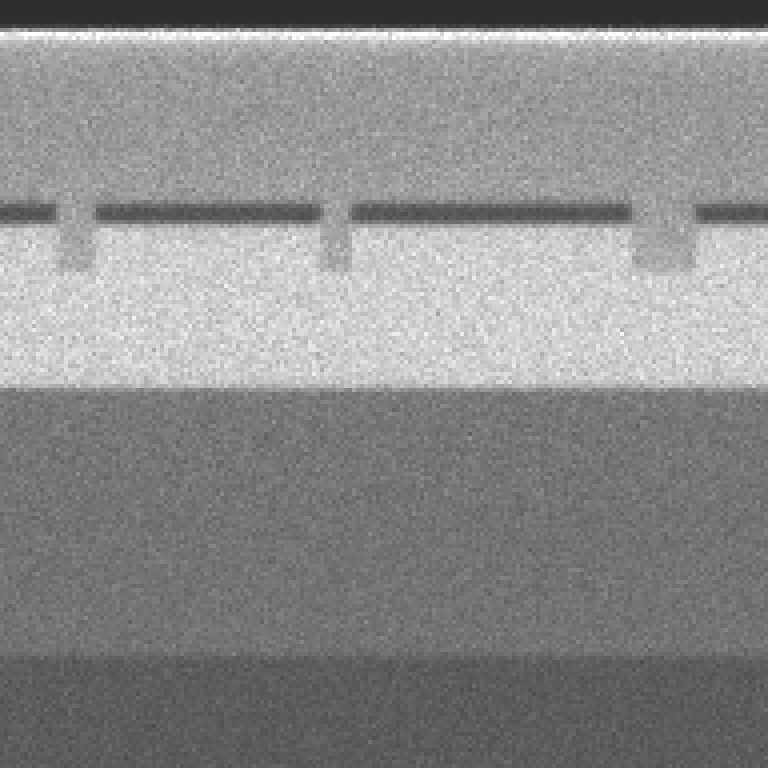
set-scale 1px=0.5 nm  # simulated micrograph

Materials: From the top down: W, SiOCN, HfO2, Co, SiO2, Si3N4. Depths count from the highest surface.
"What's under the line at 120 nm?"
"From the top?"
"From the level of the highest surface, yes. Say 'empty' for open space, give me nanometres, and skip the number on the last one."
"W 86, SiOCN 10, HfO2 82, Co 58, SiO2 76, Si3N4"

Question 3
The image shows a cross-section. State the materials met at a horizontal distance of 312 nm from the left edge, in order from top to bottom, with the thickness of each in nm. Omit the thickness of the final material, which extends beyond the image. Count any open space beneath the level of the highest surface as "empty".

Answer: W 86, SiOCN 10, HfO2 82, Co 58, SiO2 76, Si3N4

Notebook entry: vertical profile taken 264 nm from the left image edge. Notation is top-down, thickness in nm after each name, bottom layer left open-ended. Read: W 86, SiOCN 10, HfO2 82, Co 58, SiO2 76, Si3N4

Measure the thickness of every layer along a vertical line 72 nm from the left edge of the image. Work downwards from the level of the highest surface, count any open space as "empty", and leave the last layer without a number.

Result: W 86, SiOCN 10, HfO2 82, Co 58, SiO2 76, Si3N4